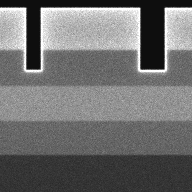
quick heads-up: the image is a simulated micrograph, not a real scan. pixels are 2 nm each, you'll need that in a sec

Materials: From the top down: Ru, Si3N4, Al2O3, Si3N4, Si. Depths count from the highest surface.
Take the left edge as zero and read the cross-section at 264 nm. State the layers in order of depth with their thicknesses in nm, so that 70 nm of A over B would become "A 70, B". Ru 84, Si3N4 72, Al2O3 70, Si3N4 68, Si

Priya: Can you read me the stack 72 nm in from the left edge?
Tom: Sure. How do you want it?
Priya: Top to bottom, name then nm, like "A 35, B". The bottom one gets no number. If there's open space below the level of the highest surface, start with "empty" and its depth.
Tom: empty 124, Si3N4 32, Al2O3 70, Si3N4 68, Si